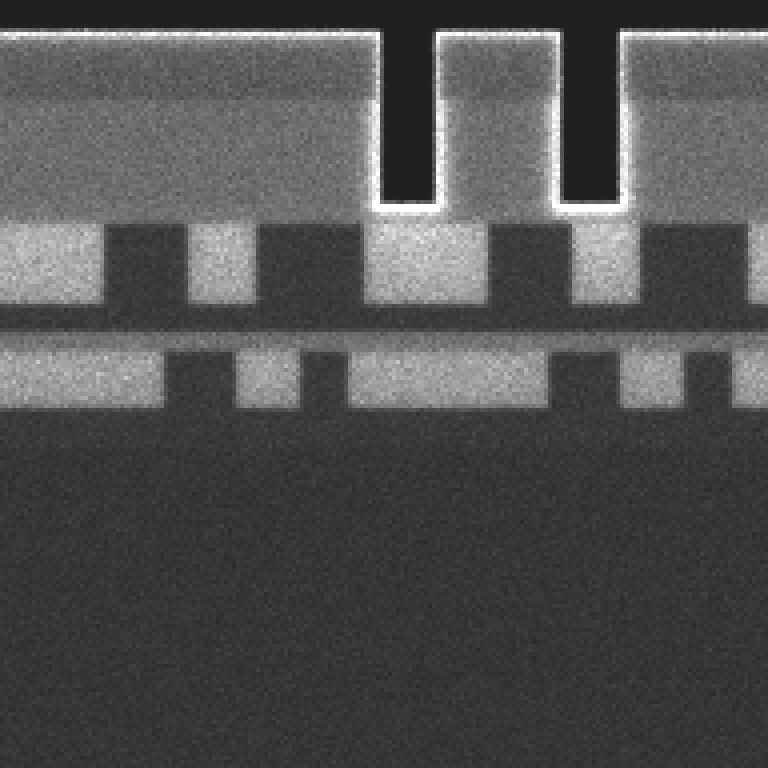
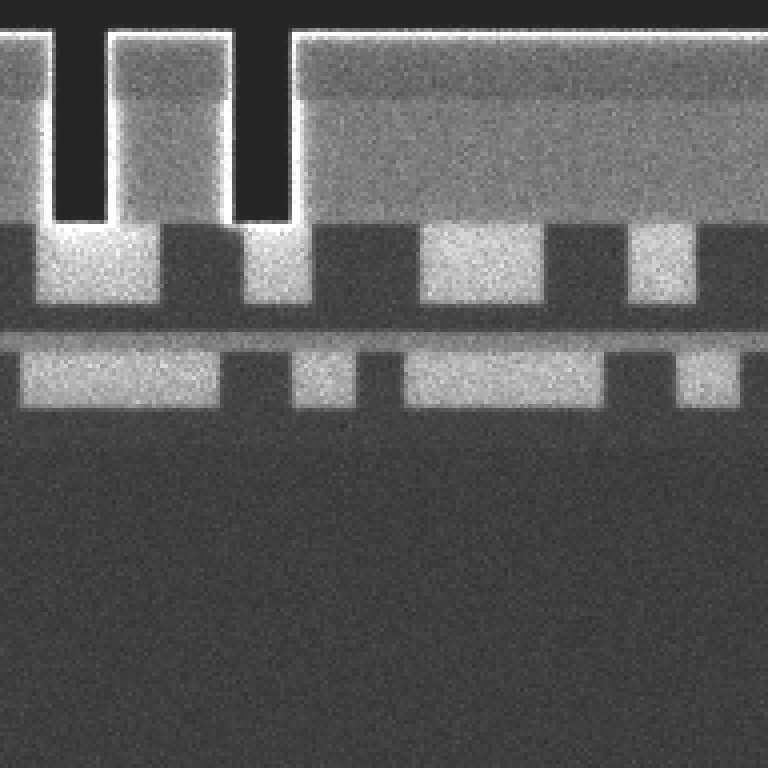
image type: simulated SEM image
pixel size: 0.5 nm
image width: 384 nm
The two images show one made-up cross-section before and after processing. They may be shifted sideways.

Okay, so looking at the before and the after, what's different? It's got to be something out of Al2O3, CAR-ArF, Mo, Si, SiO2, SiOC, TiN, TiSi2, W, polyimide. Al2O3, removed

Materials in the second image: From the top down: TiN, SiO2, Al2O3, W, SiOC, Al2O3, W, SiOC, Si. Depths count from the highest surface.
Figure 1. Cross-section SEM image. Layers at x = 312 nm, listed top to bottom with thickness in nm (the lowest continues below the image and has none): TiN 34, SiO2 52, Al2O3 10, SiOC 54, Al2O3 10, SiOC 48, Si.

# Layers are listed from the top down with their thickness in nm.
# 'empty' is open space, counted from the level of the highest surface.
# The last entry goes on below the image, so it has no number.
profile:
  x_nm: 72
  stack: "TiN 34, SiO2 52, Al2O3 10, W 40, SiOC 14, Al2O3 10, W 28, SiOC 20, Si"